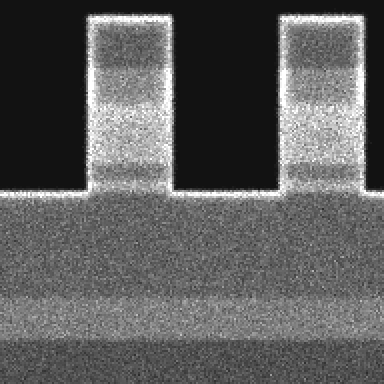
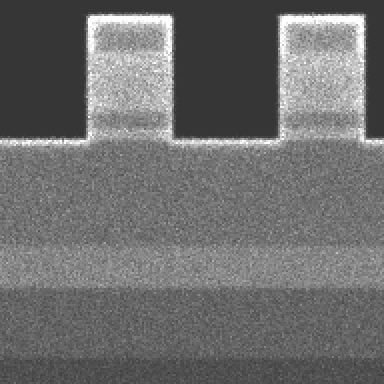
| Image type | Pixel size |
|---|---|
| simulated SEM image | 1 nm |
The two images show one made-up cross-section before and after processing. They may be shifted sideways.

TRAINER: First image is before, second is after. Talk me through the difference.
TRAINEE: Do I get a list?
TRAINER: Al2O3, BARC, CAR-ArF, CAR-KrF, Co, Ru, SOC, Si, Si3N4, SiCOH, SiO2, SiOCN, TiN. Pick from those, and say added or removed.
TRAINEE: removed: SOC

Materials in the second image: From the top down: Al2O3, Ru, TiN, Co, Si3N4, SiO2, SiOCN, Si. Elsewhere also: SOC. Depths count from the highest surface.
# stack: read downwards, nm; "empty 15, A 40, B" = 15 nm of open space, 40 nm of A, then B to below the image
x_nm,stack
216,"empty 124, Si3N4 106, SiO2 42, SiOCN 70, Si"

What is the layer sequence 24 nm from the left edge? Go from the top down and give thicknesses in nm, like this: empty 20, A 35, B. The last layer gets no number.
empty 124, Si3N4 106, SiO2 42, SiOCN 70, Si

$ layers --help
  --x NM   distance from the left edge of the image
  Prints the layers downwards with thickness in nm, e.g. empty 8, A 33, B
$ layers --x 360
Al2O3 36, Ru 60, TiN 16, Co 12, Si3N4 106, SiO2 42, SiOCN 70, Si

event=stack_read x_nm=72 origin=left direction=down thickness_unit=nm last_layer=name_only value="empty 124, Si3N4 106, SiO2 42, SiOCN 70, Si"